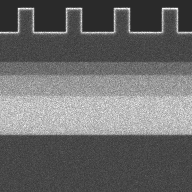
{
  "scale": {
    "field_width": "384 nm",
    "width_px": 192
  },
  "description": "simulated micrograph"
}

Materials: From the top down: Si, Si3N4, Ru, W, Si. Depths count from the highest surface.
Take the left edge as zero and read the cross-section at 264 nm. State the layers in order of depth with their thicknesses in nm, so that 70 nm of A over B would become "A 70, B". empty 48, Si 60, Si3N4 26, Ru 42, W 78, Si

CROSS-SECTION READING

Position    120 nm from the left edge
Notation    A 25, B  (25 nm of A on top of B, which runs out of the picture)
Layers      empty 48, Si 60, Si3N4 26, Ru 42, W 78, Si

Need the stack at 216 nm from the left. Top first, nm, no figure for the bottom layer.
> empty 48, Si 60, Si3N4 26, Ru 42, W 78, Si